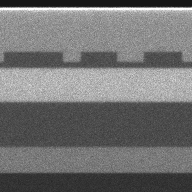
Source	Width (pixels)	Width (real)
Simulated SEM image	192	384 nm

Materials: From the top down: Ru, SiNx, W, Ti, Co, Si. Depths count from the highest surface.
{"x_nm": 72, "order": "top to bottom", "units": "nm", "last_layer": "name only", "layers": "Ru 88, SiNx 32, W 68, Ti 90, Co 52, Si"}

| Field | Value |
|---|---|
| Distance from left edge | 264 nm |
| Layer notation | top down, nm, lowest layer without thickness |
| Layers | Ru 108, SiNx 12, W 68, Ti 90, Co 52, Si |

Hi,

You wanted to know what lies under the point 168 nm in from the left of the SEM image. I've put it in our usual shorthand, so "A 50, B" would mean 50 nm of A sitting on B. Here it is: Ru 88, SiNx 32, W 68, Ti 90, Co 52, Si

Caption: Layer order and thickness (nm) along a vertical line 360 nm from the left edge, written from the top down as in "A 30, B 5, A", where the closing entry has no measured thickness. Ru 88, SiNx 32, W 68, Ti 90, Co 52, Si